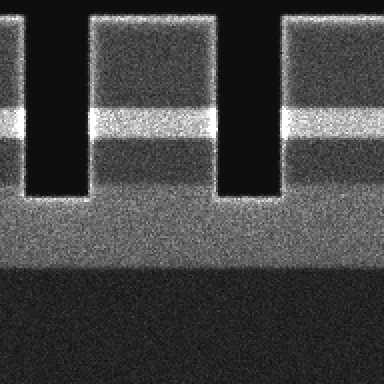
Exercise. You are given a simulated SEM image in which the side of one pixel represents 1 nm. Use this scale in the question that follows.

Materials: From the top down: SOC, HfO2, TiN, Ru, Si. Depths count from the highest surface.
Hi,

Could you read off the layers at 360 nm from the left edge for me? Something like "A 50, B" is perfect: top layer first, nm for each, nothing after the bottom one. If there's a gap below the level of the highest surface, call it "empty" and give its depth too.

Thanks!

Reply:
SOC 92, HfO2 30, TiN 46, Ru 84, Si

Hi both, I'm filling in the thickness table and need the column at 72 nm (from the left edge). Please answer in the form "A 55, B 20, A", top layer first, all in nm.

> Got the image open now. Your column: empty 182, Ru 70, Si